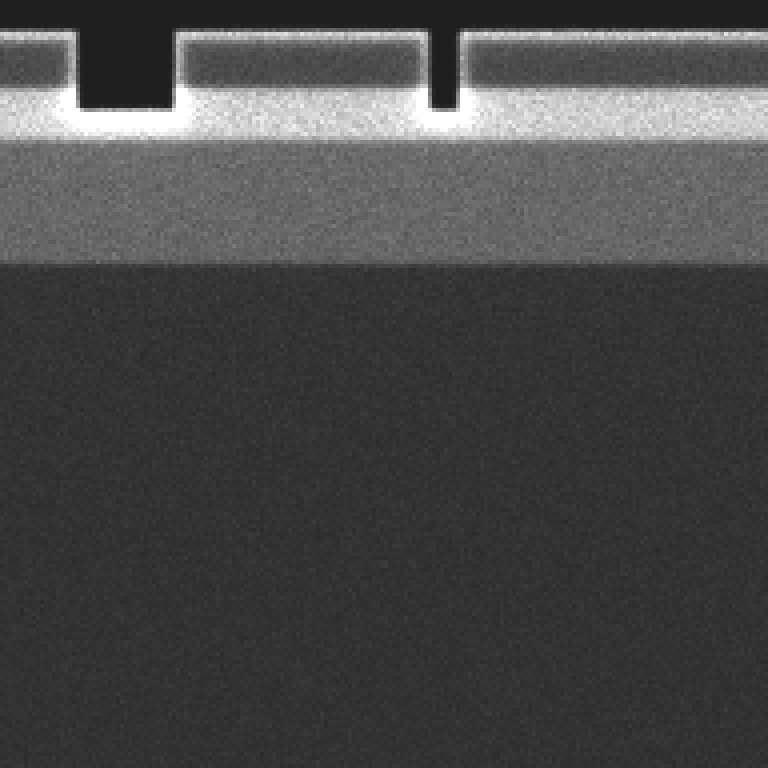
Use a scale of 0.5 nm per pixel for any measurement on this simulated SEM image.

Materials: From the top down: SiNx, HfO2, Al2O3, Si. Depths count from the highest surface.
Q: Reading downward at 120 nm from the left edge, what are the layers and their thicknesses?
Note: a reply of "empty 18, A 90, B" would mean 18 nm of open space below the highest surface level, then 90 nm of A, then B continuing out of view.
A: SiNx 28, HfO2 26, Al2O3 62, Si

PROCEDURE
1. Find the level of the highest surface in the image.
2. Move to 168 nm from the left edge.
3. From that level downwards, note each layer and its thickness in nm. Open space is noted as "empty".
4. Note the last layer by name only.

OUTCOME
SiNx 28, HfO2 26, Al2O3 62, Si